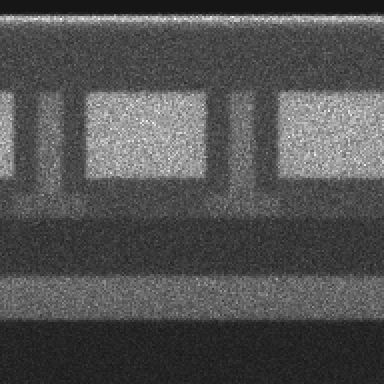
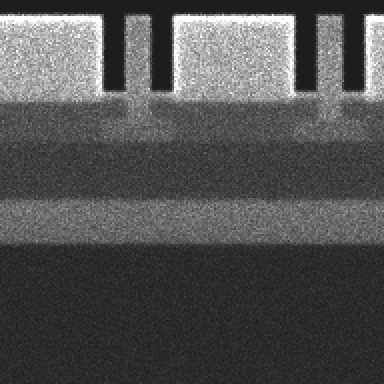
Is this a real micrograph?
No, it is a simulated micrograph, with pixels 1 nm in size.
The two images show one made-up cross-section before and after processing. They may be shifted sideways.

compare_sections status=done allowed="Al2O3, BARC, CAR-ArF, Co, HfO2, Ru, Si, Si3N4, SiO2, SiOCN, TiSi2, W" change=removed material="SiO2"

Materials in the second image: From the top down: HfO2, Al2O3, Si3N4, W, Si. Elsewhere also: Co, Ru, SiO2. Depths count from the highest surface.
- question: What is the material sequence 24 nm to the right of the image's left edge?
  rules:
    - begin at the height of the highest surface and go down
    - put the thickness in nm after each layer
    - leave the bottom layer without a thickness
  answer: HfO2 86, Al2O3 40, Si3N4 58, W 44, Si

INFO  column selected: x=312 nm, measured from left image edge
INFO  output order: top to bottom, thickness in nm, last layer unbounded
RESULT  empty 76, SiO2 26, Co 24, Si3N4 58, W 44, Si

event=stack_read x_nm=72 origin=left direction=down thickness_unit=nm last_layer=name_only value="HfO2 86, Al2O3 40, Si3N4 58, W 44, Si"